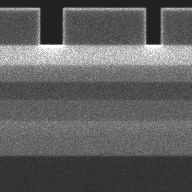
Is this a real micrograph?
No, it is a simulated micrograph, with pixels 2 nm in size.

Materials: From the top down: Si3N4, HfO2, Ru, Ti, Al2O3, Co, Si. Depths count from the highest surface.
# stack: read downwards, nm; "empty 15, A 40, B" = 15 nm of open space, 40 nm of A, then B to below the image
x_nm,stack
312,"empty 74, HfO2 40, Ru 34, Ti 36, Al2O3 42, Co 70, Si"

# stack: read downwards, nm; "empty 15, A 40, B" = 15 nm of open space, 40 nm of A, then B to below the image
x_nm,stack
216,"Si3N4 74, HfO2 40, Ru 34, Ti 36, Al2O3 42, Co 70, Si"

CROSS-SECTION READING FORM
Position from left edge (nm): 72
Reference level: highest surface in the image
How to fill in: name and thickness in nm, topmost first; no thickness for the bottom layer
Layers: Si3N4 74, HfO2 40, Ru 34, Ti 36, Al2O3 42, Co 70, Si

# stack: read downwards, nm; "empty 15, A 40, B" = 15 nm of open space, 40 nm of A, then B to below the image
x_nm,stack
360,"Si3N4 74, HfO2 40, Ru 34, Ti 36, Al2O3 42, Co 70, Si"